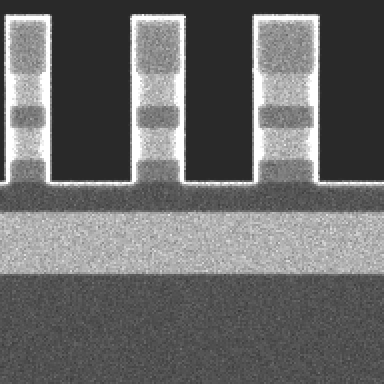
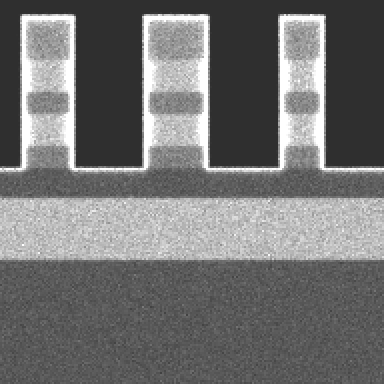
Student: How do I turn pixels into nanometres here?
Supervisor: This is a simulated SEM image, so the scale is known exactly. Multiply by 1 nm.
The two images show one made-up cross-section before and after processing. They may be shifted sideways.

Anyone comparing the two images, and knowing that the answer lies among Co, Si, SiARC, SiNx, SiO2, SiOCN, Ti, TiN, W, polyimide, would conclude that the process removed TiN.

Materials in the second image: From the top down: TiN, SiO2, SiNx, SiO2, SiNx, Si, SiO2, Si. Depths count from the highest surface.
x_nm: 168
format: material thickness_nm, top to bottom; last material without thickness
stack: TiN 44, SiO2 32, SiNx 22, SiO2 32, SiNx 22, Si 30, SiO2 62, Si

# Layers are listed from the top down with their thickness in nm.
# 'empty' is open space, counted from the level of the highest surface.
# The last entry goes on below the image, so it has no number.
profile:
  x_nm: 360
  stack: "empty 152, Si 30, SiO2 62, Si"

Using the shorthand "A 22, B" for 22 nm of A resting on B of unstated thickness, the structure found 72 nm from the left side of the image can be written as TiN 44, SiO2 32, SiNx 22, SiO2 32, SiNx 22, Si 30, SiO2 62, Si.